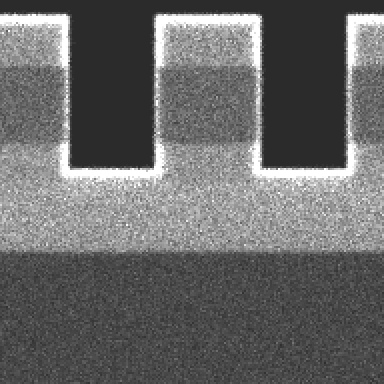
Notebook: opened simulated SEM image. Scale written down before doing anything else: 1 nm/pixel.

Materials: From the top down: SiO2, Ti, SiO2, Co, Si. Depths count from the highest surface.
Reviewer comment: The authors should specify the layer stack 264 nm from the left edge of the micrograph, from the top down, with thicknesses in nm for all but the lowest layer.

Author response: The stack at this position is empty 154, SiO2 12, Co 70, Si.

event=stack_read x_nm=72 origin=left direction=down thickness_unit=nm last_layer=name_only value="empty 154, SiO2 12, Co 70, Si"